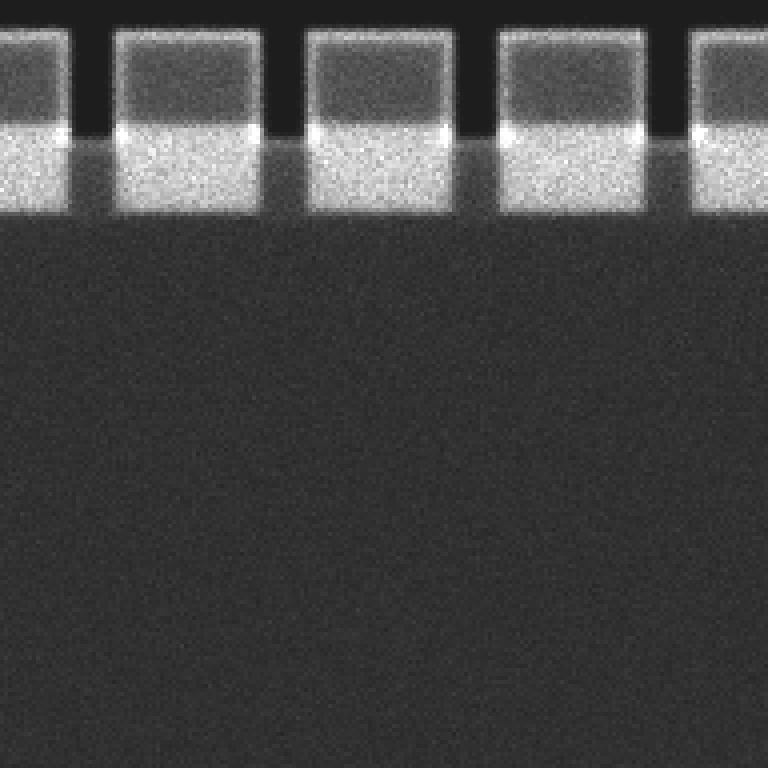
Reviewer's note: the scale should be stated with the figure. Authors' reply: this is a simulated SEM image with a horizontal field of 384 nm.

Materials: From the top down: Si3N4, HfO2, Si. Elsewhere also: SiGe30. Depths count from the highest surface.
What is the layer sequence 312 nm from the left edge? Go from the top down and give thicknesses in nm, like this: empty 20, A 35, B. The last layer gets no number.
Si3N4 46, HfO2 44, Si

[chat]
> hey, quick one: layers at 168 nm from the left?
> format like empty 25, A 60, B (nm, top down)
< Si3N4 46, HfO2 44, Si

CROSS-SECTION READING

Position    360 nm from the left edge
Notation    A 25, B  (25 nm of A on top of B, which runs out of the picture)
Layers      Si3N4 46, HfO2 44, Si